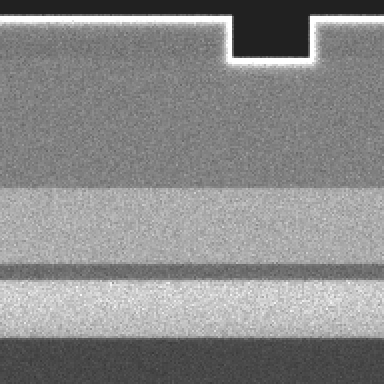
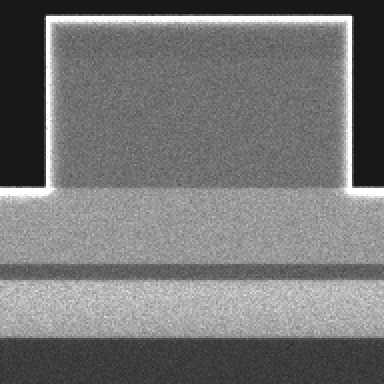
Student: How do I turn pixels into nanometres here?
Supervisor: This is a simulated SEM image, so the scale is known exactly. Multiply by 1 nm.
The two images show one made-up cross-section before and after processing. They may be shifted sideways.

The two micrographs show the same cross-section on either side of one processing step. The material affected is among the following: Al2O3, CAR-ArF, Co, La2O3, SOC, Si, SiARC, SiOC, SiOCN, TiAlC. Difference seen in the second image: SOC removed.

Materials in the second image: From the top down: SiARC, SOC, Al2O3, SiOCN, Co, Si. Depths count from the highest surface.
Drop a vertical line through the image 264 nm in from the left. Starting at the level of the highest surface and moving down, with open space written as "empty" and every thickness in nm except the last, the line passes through SiARC 42, SOC 130, Al2O3 76, SiOCN 16, Co 58, Si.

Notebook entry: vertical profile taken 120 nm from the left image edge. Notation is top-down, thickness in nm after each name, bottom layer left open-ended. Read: SiARC 42, SOC 130, Al2O3 76, SiOCN 16, Co 58, Si